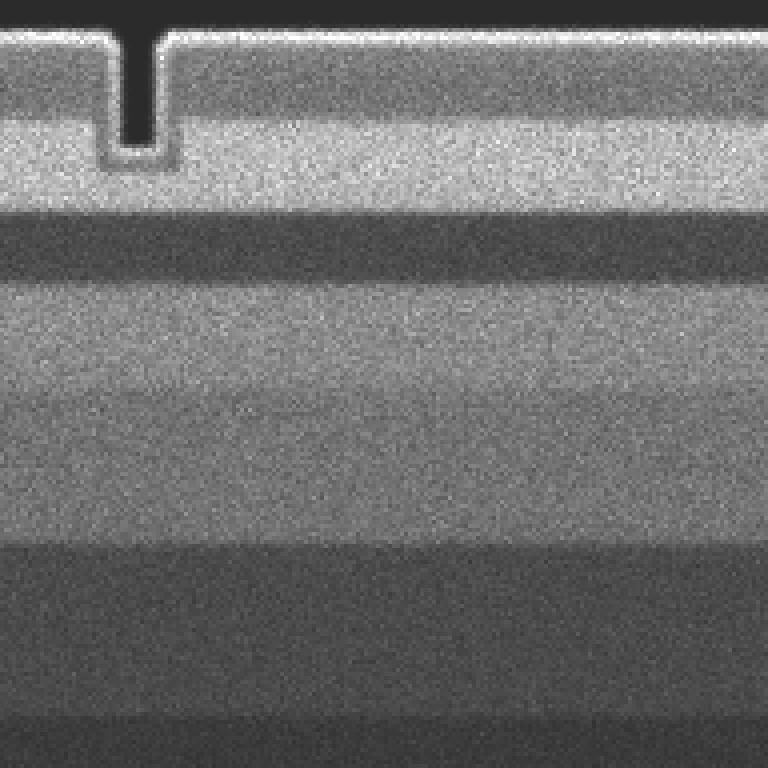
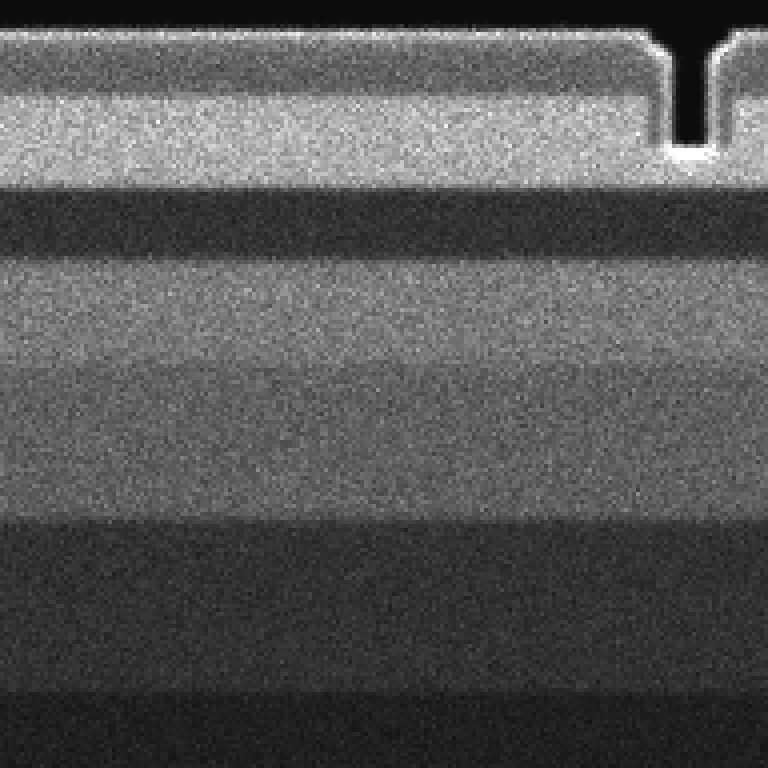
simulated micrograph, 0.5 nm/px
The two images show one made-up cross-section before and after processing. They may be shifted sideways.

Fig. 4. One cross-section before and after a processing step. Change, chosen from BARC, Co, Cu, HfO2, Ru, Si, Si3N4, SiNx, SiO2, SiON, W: SiO2 removed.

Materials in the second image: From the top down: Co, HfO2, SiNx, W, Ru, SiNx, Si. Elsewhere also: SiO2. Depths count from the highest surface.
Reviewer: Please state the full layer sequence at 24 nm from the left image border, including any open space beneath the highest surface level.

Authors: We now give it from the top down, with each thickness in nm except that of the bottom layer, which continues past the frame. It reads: Co 32, HfO2 46, SiNx 36, W 52, Ru 78, SiNx 86, Si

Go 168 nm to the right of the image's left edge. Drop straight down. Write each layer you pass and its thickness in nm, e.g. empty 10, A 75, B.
Co 32, HfO2 46, SiNx 36, W 52, Ru 78, SiNx 86, Si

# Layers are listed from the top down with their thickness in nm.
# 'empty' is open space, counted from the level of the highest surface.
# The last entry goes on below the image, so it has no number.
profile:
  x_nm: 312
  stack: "Co 32, HfO2 46, SiNx 36, W 52, Ru 78, SiNx 86, Si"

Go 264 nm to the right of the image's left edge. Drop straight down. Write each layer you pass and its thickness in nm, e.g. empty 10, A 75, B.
Co 32, HfO2 46, SiNx 36, W 52, Ru 78, SiNx 86, Si